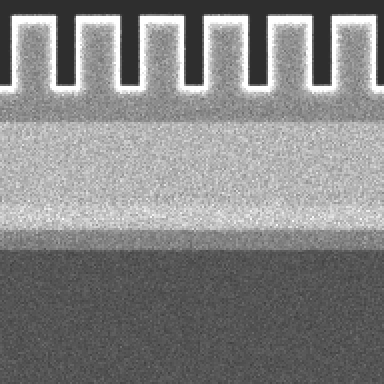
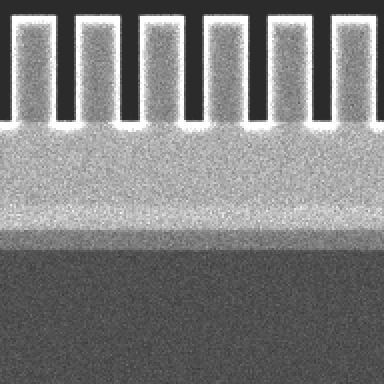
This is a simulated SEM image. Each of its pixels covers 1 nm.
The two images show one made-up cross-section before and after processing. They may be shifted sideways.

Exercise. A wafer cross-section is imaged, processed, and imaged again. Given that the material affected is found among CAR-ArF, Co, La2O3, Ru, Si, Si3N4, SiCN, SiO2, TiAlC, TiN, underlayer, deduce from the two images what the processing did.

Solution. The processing removed underlayer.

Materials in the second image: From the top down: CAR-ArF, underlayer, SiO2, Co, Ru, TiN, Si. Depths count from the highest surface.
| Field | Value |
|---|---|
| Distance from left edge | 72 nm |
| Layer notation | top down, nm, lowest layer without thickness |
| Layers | empty 106, SiO2 70, Co 14, Ru 24, TiN 20, Si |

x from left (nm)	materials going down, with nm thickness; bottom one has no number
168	CAR-ArF 70, underlayer 36, SiO2 70, Co 14, Ru 24, TiN 20, Si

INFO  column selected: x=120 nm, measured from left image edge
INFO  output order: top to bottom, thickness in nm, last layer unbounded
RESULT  empty 106, SiO2 70, Co 14, Ru 24, TiN 20, Si